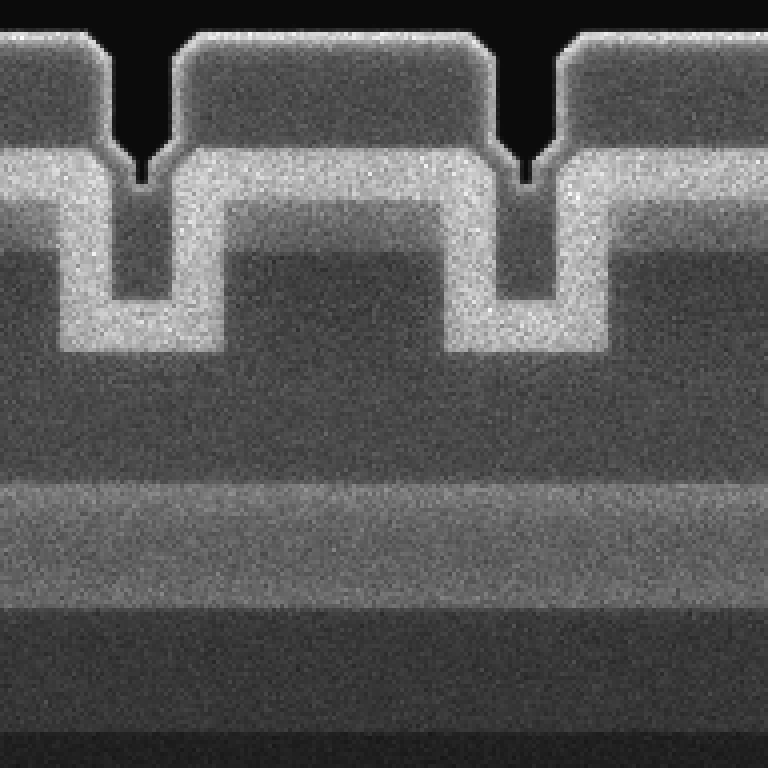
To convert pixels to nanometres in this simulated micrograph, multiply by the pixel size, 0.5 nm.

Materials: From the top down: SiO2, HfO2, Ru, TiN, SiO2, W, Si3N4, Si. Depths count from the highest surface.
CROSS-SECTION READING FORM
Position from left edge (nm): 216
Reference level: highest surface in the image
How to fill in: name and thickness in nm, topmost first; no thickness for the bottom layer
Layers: SiO2 58, HfO2 26, Ru 26, TiN 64, SiO2 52, W 62, Si3N4 62, Si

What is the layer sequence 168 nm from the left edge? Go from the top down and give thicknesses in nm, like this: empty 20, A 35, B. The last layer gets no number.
SiO2 58, HfO2 26, Ru 26, TiN 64, SiO2 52, W 62, Si3N4 62, Si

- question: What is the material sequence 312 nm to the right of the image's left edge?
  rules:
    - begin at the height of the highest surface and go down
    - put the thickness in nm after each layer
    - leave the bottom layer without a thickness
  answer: SiO2 58, HfO2 26, Ru 26, TiN 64, SiO2 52, W 62, Si3N4 62, Si